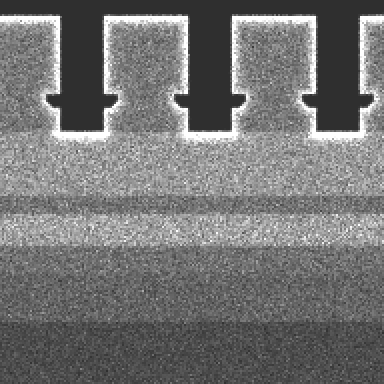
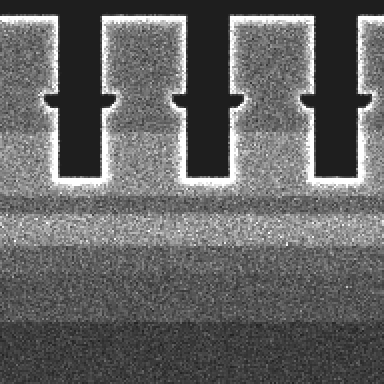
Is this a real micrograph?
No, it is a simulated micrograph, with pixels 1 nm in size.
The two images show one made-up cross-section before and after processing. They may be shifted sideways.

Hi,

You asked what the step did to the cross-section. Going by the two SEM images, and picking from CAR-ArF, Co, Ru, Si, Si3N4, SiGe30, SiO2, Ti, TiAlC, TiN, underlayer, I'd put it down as SiO2, removed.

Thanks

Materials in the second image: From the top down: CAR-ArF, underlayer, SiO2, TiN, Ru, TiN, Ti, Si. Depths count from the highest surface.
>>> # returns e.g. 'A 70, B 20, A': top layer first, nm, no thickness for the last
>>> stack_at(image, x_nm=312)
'CAR-ArF 78, empty 14, underlayer 24, SiO2 64, TiN 18, Ru 32, TiN 28, Ti 48, Si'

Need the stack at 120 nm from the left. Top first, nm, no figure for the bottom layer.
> CAR-ArF 78, underlayer 38, SiO2 64, TiN 18, Ru 32, TiN 28, Ti 48, Si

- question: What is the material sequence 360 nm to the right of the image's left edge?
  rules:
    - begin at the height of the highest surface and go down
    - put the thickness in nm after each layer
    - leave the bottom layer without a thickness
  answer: CAR-ArF 78, empty 14, underlayer 24, SiO2 64, TiN 18, Ru 32, TiN 28, Ti 48, Si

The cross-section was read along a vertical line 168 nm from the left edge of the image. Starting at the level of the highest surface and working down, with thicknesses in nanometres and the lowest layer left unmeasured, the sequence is CAR-ArF 78, underlayer 38, SiO2 64, TiN 18, Ru 32, TiN 28, Ti 48, Si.